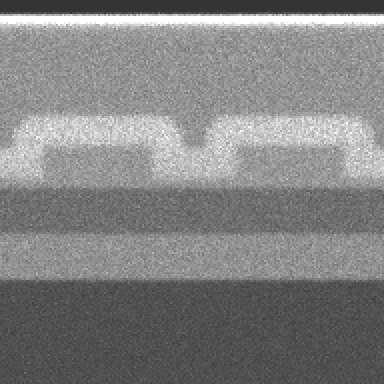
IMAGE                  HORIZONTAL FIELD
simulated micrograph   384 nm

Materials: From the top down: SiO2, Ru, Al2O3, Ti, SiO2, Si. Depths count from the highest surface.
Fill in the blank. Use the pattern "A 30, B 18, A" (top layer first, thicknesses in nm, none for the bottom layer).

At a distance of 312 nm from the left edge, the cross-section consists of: SiO2 100, Ru 30, Al2O3 42, Ti 46, SiO2 46, Si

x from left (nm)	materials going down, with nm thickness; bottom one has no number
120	SiO2 100, Ru 30, Al2O3 42, Ti 46, SiO2 46, Si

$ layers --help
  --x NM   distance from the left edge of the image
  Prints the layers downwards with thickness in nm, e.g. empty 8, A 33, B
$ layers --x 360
SiO2 102, Ru 60, Al2O3 10, Ti 46, SiO2 46, Si